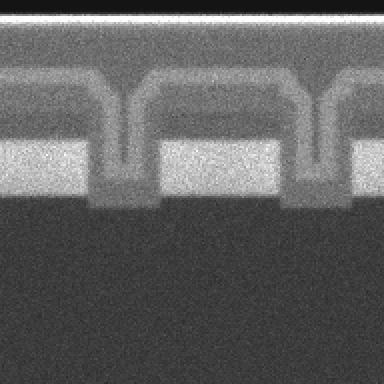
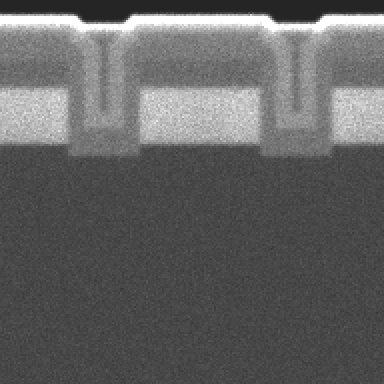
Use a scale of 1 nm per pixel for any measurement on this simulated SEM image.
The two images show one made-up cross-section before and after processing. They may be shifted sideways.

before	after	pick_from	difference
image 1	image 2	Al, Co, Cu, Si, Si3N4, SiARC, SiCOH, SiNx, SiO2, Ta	SiARC removed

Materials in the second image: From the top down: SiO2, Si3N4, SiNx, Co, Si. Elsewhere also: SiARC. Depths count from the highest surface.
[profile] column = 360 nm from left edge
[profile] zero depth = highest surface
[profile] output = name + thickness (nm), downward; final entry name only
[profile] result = SiO2 16, Si3N4 28, SiNx 28, Co 56, Si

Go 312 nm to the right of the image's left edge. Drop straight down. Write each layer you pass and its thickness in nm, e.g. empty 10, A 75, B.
empty 8, SiARC 8, SiO2 96, Si3N4 28, Si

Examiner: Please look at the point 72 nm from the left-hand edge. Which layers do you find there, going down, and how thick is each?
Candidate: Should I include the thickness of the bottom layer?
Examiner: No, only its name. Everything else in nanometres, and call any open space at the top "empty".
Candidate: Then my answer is SiO2 28, Si3N4 112, Si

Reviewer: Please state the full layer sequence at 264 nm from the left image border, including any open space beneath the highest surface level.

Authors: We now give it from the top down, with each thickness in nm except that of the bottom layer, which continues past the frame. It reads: SiO2 28, Si3N4 112, Si